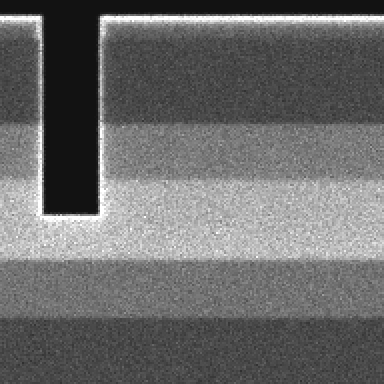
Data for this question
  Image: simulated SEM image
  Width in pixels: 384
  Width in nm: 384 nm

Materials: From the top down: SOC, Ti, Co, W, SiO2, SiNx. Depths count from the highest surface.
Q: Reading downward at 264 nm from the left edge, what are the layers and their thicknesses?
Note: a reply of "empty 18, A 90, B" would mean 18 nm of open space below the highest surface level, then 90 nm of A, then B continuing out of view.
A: SOC 22, Ti 86, Co 56, W 80, SiO2 58, SiNx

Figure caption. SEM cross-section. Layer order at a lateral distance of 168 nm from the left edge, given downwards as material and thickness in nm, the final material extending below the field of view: SOC 22, Ti 86, Co 56, W 80, SiO2 58, SiNx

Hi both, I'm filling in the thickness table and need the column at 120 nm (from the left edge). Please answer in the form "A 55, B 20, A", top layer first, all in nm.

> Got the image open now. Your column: SOC 22, Ti 86, Co 56, W 80, SiO2 58, SiNx